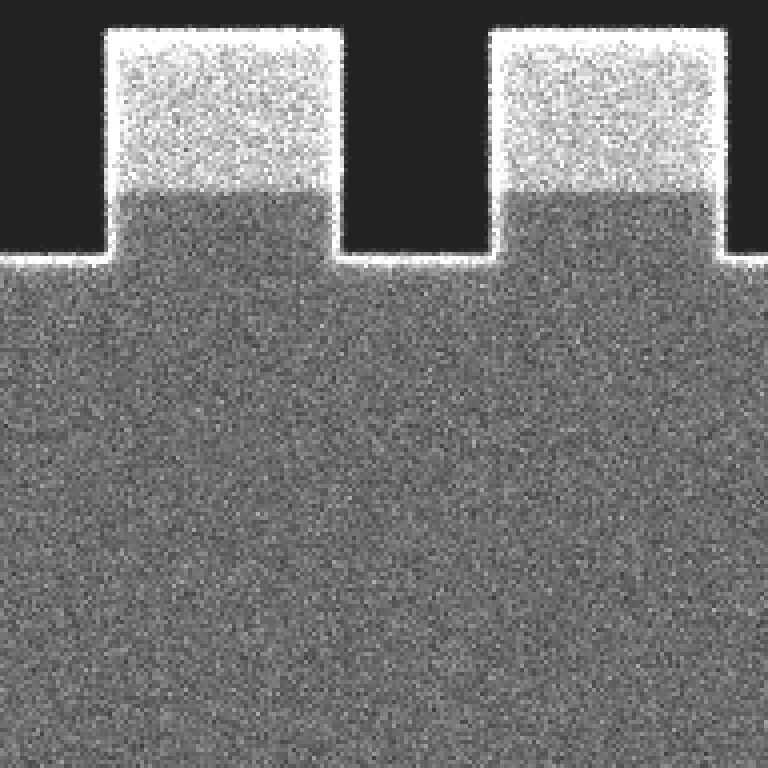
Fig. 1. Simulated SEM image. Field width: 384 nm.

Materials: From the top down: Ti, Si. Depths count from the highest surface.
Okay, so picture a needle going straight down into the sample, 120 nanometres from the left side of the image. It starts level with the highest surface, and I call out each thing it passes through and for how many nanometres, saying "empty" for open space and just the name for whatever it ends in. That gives Ti 80, Si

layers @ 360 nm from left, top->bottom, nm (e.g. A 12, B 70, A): Ti 80, Si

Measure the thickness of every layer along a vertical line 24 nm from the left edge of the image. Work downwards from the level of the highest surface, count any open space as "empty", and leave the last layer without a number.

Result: empty 112, Si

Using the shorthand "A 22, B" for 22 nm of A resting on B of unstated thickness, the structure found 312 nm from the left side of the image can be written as Ti 80, Si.